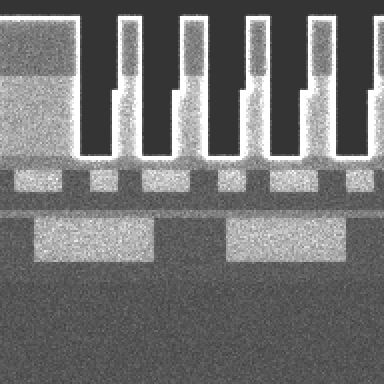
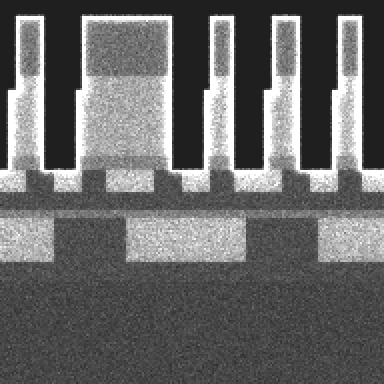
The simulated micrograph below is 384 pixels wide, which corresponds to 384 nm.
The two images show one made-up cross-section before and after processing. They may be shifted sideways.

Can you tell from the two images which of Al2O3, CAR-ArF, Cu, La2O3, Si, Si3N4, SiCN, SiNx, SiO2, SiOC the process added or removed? Yes, it removed Si3N4.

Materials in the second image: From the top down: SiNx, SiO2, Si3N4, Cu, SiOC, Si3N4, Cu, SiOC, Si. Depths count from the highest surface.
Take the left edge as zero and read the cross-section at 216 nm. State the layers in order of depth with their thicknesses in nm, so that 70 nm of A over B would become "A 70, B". SiNx 60, SiO2 80, Si3N4 14, SiOC 40, Si3N4 8, Cu 44, SiOC 20, Si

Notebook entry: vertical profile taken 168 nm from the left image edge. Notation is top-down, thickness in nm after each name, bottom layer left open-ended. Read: SiNx 60, SiO2 80, Si3N4 14, SiOC 40, Si3N4 8, Cu 44, SiOC 20, Si